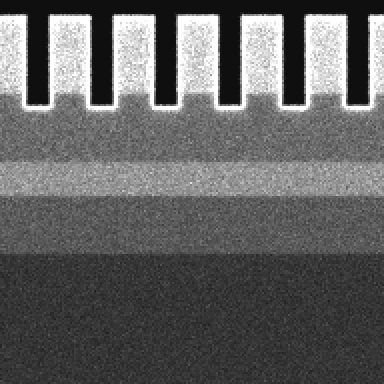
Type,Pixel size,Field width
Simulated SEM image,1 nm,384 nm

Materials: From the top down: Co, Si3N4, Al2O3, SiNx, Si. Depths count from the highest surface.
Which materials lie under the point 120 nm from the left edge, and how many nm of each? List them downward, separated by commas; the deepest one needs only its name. Co 78, Si3N4 68, Al2O3 34, SiNx 58, Si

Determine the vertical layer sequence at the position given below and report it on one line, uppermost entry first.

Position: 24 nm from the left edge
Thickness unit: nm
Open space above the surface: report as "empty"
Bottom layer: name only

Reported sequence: Co 78, Si3N4 68, Al2O3 34, SiNx 58, Si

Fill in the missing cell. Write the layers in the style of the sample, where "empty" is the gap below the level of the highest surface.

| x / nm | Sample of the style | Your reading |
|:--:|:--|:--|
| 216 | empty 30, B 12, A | Co 78, Si3N4 68, Al2O3 34, SiNx 58, Si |